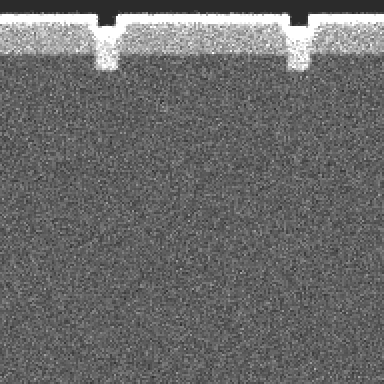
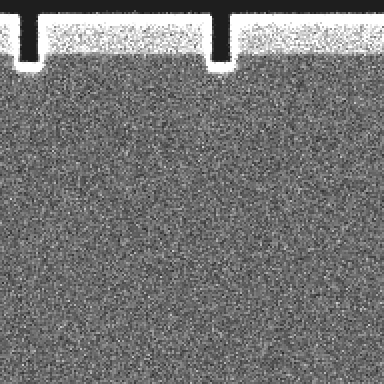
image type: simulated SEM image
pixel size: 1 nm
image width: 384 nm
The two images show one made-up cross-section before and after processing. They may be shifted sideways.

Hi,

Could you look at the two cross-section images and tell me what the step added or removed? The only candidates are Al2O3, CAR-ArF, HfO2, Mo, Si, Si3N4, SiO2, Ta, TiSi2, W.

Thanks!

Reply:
removed SiO2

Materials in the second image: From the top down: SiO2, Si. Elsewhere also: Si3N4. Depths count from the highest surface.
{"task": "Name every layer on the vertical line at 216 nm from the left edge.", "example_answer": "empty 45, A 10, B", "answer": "empty 48, SiO2 6, Si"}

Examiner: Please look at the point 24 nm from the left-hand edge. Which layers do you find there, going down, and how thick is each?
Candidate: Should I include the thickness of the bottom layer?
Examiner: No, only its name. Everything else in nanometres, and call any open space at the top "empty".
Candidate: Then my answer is empty 48, SiO2 6, Si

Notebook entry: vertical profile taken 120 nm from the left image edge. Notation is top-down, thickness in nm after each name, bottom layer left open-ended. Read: Si3N4 38, Si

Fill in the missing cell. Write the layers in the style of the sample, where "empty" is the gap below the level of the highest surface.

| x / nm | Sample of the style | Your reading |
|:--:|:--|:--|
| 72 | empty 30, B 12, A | Si3N4 38, Si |